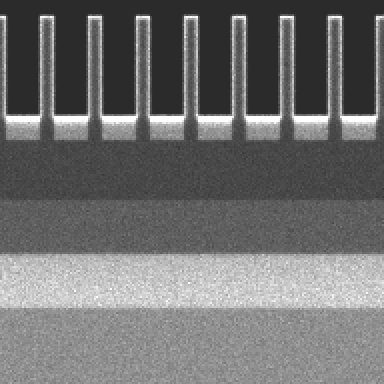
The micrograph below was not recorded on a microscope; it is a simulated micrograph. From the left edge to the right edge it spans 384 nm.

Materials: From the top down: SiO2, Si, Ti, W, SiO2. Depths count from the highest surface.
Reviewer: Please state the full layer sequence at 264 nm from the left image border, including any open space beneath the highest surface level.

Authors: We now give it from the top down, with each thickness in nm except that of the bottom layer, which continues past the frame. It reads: empty 100, SiO2 24, Si 60, Ti 54, W 54, SiO2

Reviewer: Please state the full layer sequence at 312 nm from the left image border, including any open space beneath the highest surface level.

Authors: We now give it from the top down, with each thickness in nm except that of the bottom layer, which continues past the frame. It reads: empty 100, SiO2 24, Si 60, Ti 54, W 54, SiO2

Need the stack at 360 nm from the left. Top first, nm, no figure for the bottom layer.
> empty 100, SiO2 24, Si 60, Ti 54, W 54, SiO2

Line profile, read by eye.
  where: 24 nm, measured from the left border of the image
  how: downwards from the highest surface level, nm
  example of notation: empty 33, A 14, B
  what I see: empty 100, SiO2 24, Si 60, Ti 54, W 54, SiO2